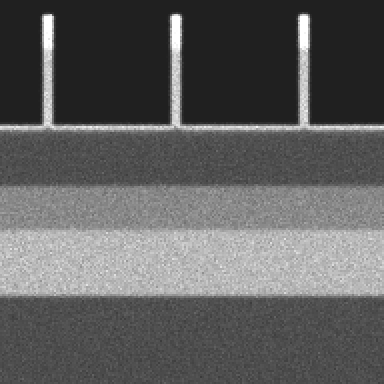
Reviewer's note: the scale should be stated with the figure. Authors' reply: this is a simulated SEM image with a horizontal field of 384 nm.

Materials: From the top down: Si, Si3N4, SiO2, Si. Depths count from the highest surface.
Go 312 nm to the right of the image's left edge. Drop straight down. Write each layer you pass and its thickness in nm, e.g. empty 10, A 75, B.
empty 110, Si 60, Si3N4 44, SiO2 66, Si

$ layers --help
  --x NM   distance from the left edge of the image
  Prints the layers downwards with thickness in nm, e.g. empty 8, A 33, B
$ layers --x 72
empty 110, Si 60, Si3N4 44, SiO2 66, Si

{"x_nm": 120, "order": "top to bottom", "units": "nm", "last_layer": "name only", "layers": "empty 110, Si 60, Si3N4 44, SiO2 66, Si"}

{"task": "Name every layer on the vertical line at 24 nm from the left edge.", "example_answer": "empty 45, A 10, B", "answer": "empty 110, Si 60, Si3N4 44, SiO2 66, Si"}